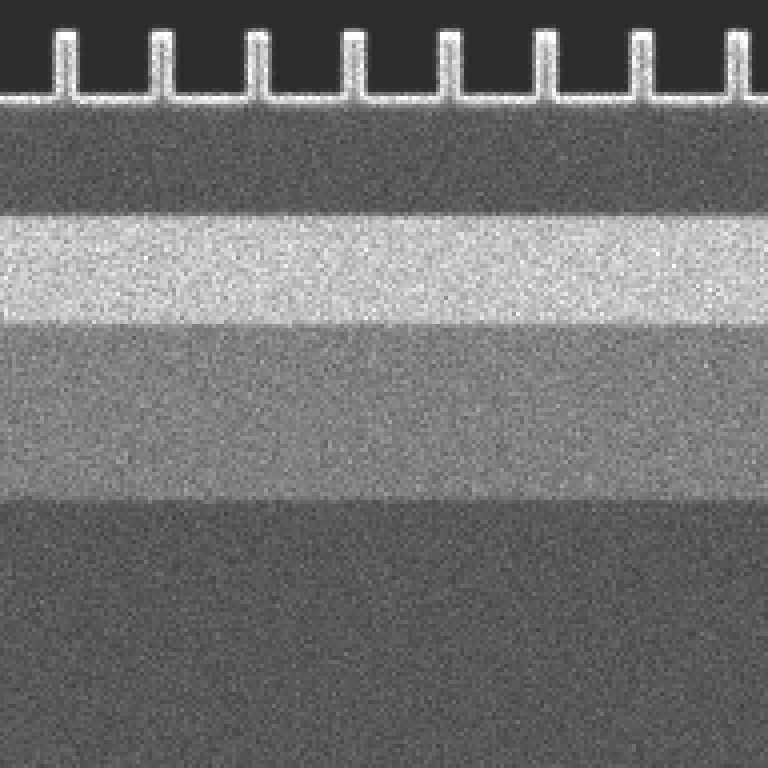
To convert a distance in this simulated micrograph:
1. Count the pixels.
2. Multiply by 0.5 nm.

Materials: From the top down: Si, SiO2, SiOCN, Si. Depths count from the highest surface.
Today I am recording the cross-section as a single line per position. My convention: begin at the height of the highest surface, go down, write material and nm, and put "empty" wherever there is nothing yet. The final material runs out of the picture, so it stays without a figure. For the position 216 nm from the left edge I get empty 32, Si 60, SiO2 54, SiOCN 88, Si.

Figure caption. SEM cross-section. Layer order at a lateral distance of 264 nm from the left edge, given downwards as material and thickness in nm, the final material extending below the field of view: empty 32, Si 60, SiO2 54, SiOCN 88, Si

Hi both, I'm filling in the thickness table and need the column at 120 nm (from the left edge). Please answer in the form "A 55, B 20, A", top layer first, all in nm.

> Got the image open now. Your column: empty 32, Si 60, SiO2 54, SiOCN 88, Si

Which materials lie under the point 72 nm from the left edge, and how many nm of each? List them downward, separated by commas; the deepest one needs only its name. empty 32, Si 60, SiO2 54, SiOCN 88, Si